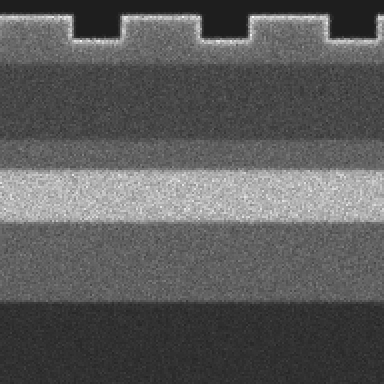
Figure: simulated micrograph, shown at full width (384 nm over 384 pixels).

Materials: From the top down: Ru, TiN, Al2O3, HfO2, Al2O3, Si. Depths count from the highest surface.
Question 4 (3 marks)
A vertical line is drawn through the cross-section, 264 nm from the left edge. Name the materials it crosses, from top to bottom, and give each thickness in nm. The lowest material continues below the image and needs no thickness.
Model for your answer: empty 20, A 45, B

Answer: Ru 48, TiN 76, Al2O3 30, HfO2 52, Al2O3 80, Si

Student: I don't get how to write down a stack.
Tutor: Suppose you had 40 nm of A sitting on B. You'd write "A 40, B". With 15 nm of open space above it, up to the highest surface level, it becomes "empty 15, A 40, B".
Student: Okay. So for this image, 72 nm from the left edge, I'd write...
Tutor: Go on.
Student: empty 24, Ru 24, TiN 76, Al2O3 30, HfO2 52, Al2O3 80, Si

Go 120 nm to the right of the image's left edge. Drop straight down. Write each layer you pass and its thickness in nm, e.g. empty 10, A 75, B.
empty 24, Ru 24, TiN 76, Al2O3 30, HfO2 52, Al2O3 80, Si